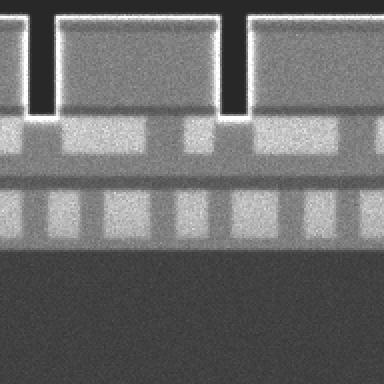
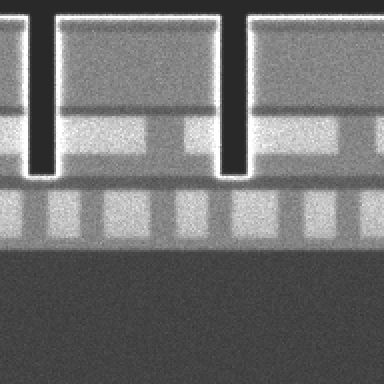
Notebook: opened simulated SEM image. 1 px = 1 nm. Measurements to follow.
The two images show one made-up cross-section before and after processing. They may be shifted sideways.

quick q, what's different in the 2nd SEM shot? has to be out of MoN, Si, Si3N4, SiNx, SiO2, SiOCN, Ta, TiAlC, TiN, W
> SiO2 removed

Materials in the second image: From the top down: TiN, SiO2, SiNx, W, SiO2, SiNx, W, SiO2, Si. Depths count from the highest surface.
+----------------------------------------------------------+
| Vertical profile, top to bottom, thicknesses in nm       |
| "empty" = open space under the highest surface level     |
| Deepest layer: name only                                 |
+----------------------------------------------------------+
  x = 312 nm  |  TiN 16, SiO2 74, SiNx 10, W 38, SiO2 22, SiNx 14, W 48, SiO2 12, Si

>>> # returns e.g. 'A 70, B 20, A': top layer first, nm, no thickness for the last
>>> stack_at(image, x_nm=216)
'TiN 16, SiO2 74, SiNx 10, SiO2 60, SiNx 14, SiO2 60, Si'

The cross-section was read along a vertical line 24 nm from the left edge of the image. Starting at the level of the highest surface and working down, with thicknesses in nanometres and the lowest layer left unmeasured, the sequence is TiN 16, SiO2 74, SiNx 10, SiO2 60, SiNx 14, SiO2 60, Si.